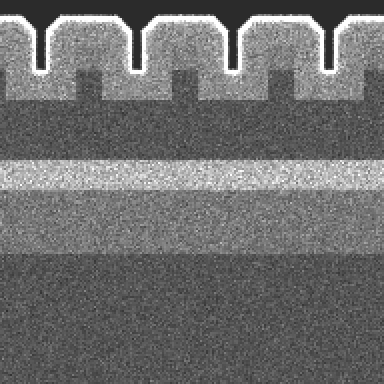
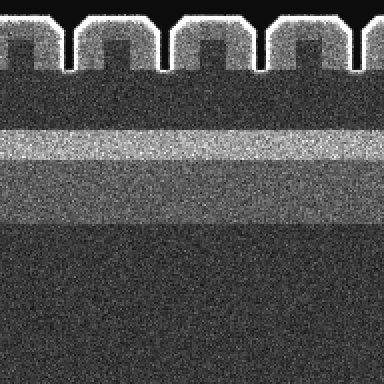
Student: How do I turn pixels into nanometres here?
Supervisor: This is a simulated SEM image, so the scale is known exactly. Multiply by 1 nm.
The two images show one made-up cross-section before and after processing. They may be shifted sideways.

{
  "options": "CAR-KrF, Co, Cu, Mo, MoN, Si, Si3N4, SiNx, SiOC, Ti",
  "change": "removed",
  "material": "Si3N4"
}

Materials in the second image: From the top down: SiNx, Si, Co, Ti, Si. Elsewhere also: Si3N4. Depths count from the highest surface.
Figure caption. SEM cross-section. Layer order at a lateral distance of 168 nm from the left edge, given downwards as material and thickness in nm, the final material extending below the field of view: empty 54, Si 60, Co 30, Ti 64, Si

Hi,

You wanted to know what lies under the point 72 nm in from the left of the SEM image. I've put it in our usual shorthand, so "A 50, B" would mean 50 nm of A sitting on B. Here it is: empty 54, Si 60, Co 30, Ti 64, Si